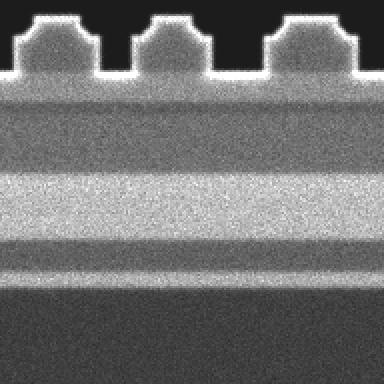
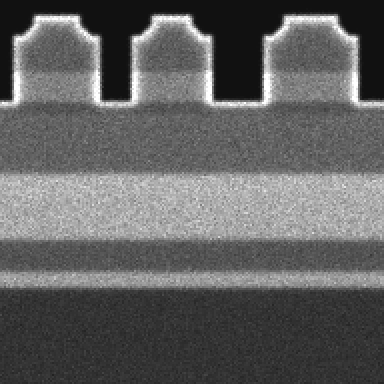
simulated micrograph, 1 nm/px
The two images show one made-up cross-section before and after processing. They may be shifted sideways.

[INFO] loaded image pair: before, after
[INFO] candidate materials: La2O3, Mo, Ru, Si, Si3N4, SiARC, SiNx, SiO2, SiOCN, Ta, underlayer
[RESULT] removed SiO2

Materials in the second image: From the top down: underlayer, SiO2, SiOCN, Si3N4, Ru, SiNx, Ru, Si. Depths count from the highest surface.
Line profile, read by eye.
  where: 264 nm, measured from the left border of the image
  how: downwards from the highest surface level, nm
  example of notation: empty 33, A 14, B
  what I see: empty 20, underlayer 36, SiO2 30, SiOCN 12, Si3N4 60, Ru 66, SiNx 32, Ru 16, Si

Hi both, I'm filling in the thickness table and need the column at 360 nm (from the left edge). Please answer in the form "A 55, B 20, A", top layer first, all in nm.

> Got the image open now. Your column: empty 86, SiOCN 12, Si3N4 60, Ru 66, SiNx 32, Ru 16, Si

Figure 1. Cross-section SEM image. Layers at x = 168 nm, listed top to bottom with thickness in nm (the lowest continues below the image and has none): underlayer 56, SiO2 30, SiOCN 12, Si3N4 60, Ru 66, SiNx 32, Ru 16, Si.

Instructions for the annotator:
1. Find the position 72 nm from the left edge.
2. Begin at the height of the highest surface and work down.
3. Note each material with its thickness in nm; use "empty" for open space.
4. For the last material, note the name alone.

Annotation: underlayer 56, SiO2 30, SiOCN 12, Si3N4 60, Ru 66, SiNx 32, Ru 16, Si